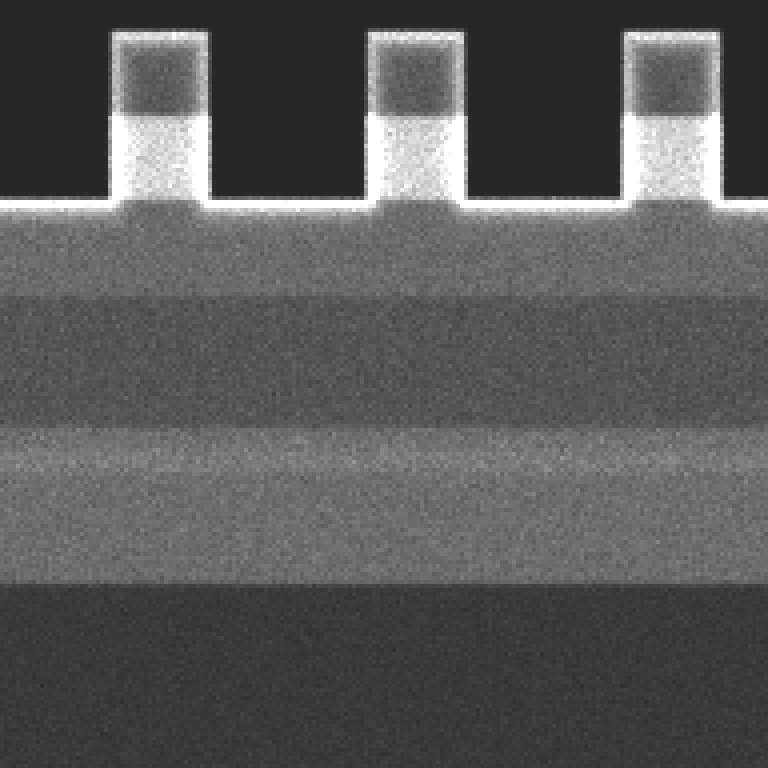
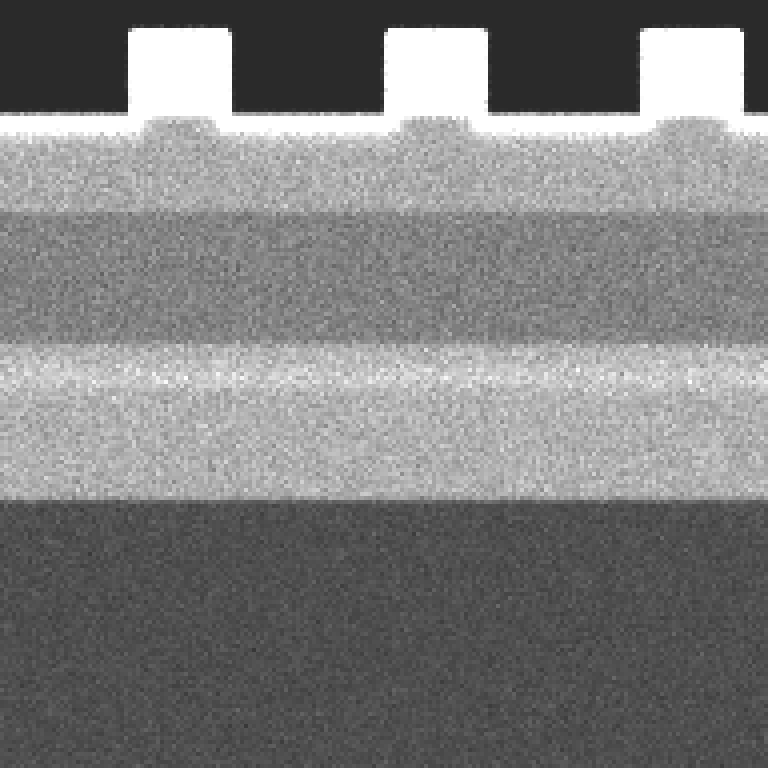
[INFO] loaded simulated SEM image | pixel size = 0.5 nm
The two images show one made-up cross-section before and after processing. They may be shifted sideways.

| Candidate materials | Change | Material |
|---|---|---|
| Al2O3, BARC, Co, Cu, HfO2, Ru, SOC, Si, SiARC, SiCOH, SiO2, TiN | removed | SOC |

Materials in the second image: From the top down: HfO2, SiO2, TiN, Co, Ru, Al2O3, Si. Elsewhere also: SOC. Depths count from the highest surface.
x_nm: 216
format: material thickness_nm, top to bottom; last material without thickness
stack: HfO2 42, SiO2 48, TiN 66, Co 12, Ru 10, Al2O3 56, Si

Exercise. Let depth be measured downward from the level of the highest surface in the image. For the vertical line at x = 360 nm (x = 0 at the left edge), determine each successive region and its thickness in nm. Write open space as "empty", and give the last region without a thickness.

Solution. HfO2 42, SiO2 48, TiN 66, Co 12, Ru 10, Al2O3 56, Si